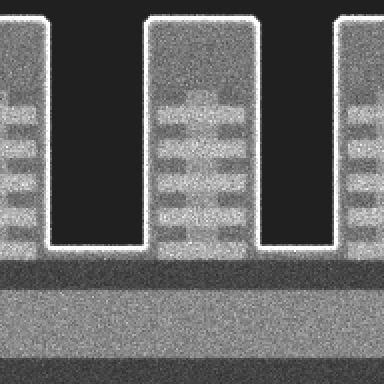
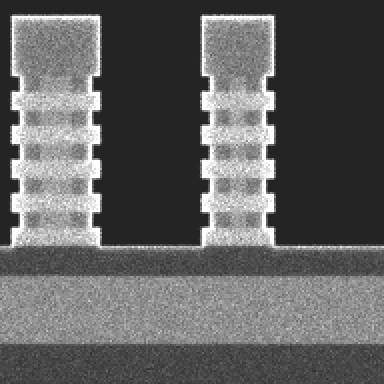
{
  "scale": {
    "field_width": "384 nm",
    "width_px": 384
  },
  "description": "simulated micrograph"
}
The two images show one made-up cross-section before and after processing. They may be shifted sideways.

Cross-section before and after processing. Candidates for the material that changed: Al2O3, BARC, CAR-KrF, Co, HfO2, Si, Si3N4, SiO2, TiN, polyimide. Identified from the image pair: Si3N4 (removed).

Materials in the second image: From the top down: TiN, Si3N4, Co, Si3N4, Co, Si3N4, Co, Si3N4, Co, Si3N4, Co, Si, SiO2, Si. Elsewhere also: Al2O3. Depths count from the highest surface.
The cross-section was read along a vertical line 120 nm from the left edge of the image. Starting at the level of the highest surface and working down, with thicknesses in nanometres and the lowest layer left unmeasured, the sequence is empty 230, Si 30, SiO2 68, Si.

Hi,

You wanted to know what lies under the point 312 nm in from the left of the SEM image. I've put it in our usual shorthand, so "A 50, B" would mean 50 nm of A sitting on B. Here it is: empty 230, Si 30, SiO2 68, Si